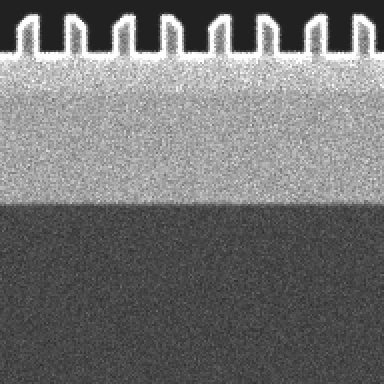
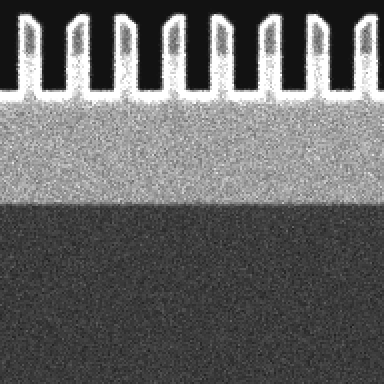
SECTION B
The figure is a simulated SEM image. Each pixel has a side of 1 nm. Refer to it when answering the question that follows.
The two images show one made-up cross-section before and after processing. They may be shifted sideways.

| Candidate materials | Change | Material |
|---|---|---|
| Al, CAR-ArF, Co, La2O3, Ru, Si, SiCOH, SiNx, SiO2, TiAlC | removed | Co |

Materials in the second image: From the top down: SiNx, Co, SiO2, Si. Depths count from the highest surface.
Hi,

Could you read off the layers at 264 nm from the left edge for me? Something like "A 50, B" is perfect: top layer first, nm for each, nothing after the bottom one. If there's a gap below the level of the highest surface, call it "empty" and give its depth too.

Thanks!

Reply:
empty 6, SiNx 32, Co 38, SiO2 112, Si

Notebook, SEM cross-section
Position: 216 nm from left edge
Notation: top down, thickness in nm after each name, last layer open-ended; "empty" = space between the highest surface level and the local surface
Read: SiNx 38, Co 38, SiO2 112, Si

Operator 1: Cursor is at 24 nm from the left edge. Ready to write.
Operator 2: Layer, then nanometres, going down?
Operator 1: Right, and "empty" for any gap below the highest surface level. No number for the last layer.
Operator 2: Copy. SiNx 38, Co 38, SiO2 112, Si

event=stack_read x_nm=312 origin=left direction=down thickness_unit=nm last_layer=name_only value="SiNx 38, Co 38, SiO2 112, Si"